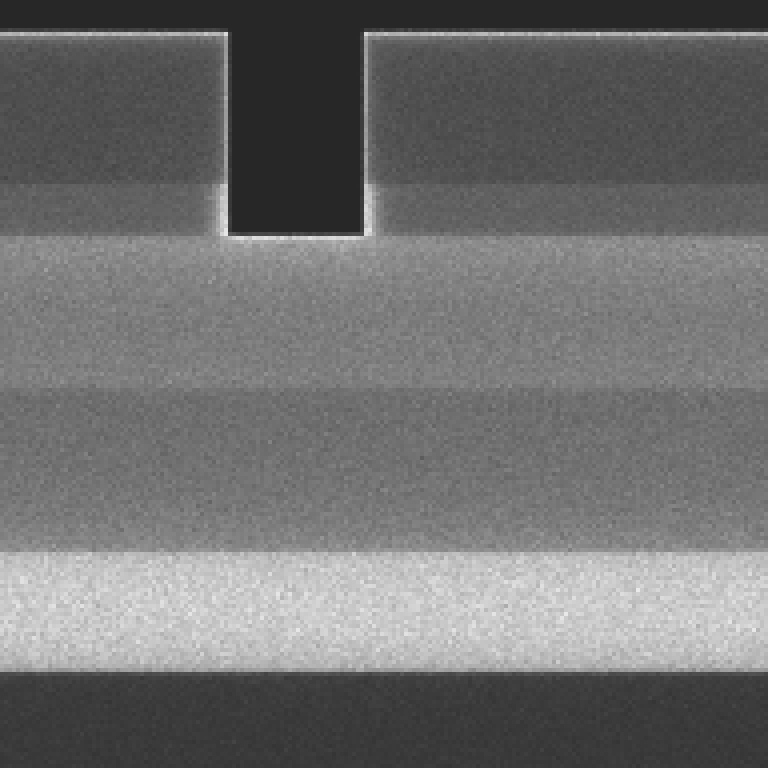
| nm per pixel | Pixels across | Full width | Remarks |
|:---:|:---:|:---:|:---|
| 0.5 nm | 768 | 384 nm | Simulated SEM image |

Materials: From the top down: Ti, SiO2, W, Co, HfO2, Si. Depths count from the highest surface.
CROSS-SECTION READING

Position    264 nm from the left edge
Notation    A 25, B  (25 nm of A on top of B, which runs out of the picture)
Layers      Ti 76, SiO2 26, W 76, Co 82, HfO2 60, Si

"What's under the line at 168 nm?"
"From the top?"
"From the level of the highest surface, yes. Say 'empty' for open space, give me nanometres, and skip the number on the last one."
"empty 102, W 76, Co 82, HfO2 60, Si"